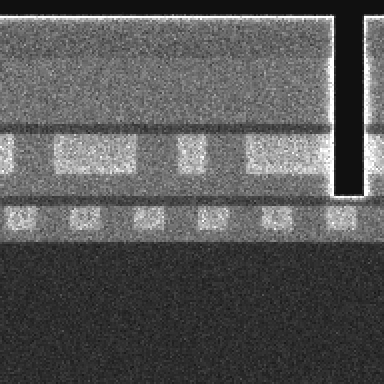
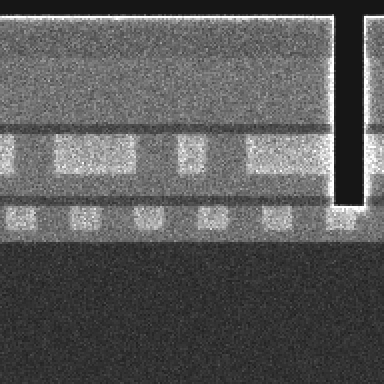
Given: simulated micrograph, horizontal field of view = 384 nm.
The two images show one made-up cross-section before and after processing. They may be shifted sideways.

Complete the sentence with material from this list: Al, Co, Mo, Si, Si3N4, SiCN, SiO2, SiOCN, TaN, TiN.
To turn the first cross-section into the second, SiCN must be removed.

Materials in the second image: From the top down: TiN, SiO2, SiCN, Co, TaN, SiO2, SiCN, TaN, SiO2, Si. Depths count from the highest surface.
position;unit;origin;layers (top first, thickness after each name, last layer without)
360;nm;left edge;empty 190, SiO2 36, Si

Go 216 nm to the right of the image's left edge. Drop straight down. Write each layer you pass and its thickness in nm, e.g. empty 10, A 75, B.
TiN 42, SiO2 66, SiCN 10, SiO2 62, SiCN 10, Co 16, TaN 8, SiO2 12, Si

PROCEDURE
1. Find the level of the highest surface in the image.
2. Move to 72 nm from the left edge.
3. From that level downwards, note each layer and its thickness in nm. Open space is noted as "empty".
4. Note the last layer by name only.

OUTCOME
TiN 42, SiO2 66, SiCN 10, Co 32, TaN 8, SiO2 22, SiCN 10, TaN 24, SiO2 12, Si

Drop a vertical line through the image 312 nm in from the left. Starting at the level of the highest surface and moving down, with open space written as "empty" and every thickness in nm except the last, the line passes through TiN 42, SiO2 66, SiCN 10, Co 32, TaN 8, SiO2 22, SiCN 10, SiO2 36, Si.